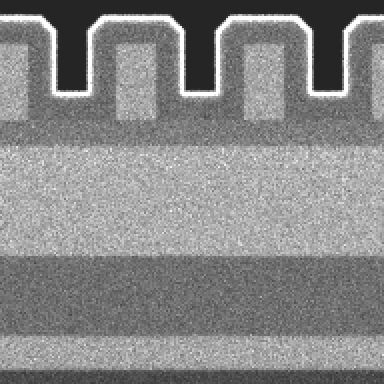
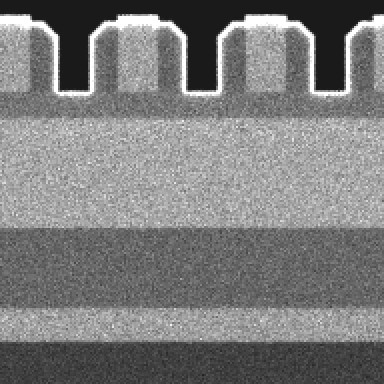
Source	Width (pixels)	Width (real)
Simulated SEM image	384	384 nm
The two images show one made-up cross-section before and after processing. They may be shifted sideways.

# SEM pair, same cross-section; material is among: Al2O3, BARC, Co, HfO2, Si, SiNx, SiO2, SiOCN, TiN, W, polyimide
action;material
removed;SiOCN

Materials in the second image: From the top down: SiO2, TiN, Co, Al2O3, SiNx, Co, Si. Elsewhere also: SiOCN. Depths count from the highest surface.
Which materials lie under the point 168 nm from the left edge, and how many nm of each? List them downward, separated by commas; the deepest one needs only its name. empty 6, SiOCN 70, TiN 26, Co 24, Al2O3 86, SiNx 80, Co 34, Si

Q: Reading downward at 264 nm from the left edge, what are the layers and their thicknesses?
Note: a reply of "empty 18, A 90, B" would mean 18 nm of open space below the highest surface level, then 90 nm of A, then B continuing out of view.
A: SiO2 76, TiN 26, Co 24, Al2O3 86, SiNx 80, Co 34, Si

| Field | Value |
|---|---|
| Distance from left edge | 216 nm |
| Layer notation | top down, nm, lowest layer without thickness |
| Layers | empty 76, TiN 26, Co 24, Al2O3 86, SiNx 80, Co 34, Si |